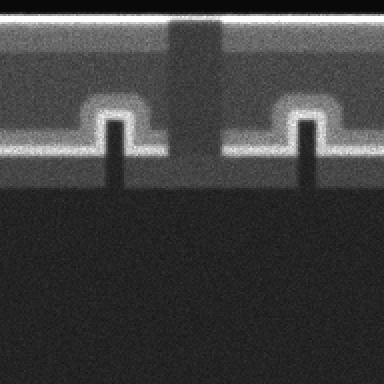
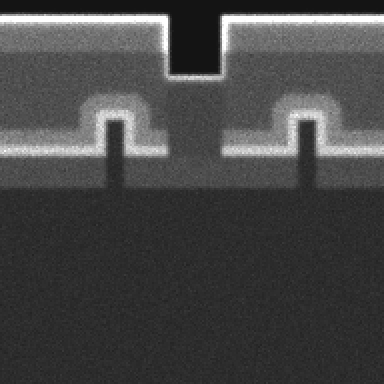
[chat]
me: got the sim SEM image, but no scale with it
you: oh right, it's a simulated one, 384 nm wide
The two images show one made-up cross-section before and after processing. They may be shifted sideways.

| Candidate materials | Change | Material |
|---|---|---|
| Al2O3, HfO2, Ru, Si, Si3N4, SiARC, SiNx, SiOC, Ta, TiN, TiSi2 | removed | SiNx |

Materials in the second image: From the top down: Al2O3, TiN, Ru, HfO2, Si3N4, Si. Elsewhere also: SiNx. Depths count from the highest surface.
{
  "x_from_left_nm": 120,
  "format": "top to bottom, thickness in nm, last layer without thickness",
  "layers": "Al2O3 36, TiN 42, Ru 16, HfO2 10, Si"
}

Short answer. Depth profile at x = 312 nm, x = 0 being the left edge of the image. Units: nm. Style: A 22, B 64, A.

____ Al2O3 36, TiN 42, Ru 16, HfO2 10, Si